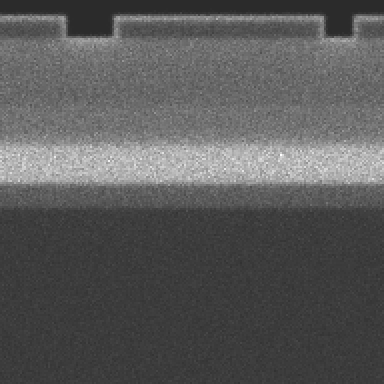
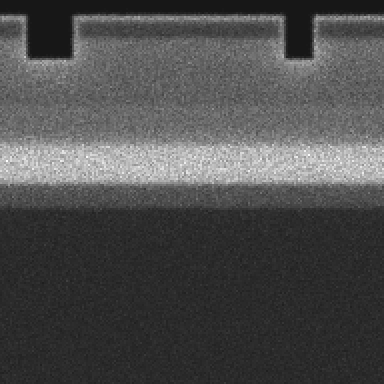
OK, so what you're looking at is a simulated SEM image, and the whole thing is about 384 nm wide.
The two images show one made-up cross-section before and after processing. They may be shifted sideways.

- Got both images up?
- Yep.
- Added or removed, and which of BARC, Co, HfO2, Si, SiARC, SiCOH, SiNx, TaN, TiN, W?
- removed, Co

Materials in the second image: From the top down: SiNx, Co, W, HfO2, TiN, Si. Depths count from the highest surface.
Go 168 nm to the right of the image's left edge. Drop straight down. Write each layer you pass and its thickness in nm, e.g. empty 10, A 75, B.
SiNx 22, Co 68, W 40, HfO2 38, TiN 24, Si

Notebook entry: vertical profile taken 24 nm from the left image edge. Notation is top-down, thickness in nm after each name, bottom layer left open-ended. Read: SiNx 22, Co 68, W 40, HfO2 38, TiN 24, Si